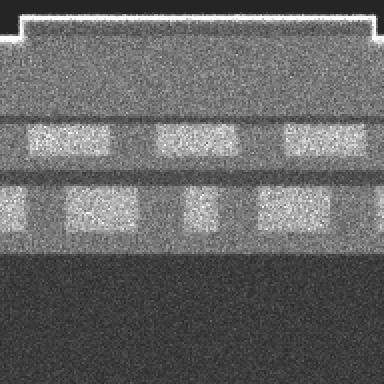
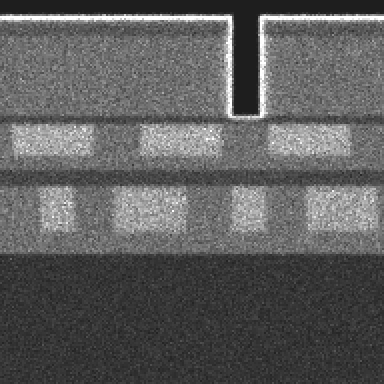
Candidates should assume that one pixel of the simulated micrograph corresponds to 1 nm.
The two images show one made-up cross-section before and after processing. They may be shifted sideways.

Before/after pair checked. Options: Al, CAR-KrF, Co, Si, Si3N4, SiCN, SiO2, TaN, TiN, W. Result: removed SiO2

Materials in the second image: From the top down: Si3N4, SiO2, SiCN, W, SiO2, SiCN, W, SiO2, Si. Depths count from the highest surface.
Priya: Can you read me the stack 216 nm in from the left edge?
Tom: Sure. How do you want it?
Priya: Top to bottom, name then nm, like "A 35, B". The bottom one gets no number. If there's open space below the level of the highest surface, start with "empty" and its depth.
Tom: Si3N4 20, SiO2 80, SiCN 8, W 32, SiO2 14, SiCN 16, SiO2 68, Si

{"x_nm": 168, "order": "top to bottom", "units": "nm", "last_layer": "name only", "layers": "Si3N4 20, SiO2 80, SiCN 8, W 32, SiO2 14, SiCN 16, W 46, SiO2 22, Si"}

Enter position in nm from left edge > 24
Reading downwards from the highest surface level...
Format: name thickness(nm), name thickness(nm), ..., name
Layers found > Si3N4 20, SiO2 80, SiCN 8, W 32, SiO2 14, SiCN 16, SiO2 68, Si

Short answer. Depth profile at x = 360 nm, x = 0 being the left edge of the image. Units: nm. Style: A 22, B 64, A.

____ Si3N4 20, SiO2 80, SiCN 8, SiO2 46, SiCN 16, W 46, SiO2 22, Si